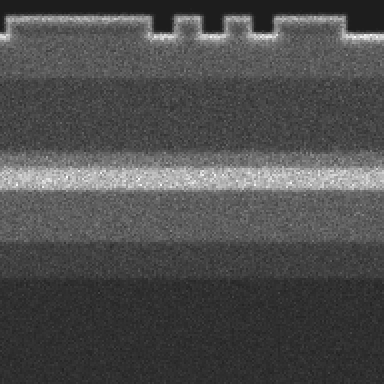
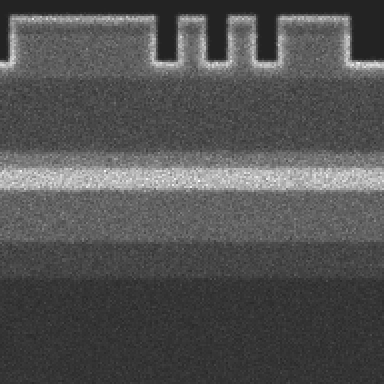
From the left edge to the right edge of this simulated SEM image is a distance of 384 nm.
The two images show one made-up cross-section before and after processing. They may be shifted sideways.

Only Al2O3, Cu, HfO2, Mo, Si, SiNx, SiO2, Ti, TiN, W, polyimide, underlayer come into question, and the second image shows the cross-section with SiO2 removed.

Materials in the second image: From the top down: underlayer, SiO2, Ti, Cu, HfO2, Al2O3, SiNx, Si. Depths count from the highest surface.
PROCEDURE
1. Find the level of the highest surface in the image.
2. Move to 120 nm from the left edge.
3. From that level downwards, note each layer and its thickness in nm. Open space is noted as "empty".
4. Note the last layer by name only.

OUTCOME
underlayer 18, SiO2 44, Ti 74, Cu 16, HfO2 22, Al2O3 52, SiNx 36, Si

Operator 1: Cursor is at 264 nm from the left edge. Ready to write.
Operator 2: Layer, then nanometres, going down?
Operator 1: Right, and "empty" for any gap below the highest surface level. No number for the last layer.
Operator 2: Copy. empty 46, SiO2 16, Ti 74, Cu 16, HfO2 22, Al2O3 52, SiNx 36, Si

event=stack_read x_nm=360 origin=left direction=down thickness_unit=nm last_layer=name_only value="empty 46, SiO2 16, Ti 74, Cu 16, HfO2 22, Al2O3 52, SiNx 36, Si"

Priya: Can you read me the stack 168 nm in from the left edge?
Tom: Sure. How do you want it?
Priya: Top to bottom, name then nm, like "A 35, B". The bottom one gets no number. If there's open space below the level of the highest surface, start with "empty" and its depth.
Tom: empty 46, SiO2 16, Ti 74, Cu 16, HfO2 22, Al2O3 52, SiNx 36, Si